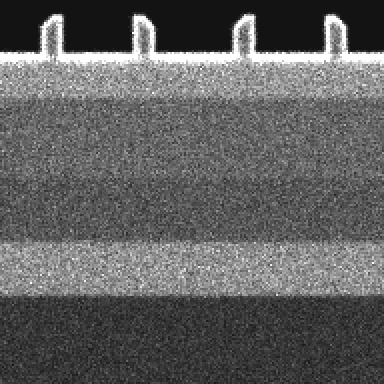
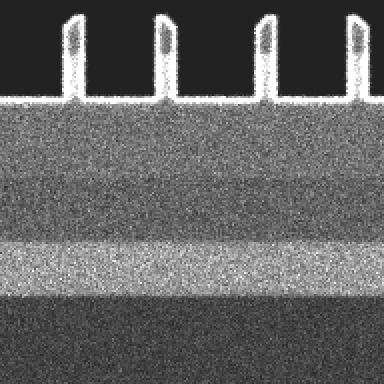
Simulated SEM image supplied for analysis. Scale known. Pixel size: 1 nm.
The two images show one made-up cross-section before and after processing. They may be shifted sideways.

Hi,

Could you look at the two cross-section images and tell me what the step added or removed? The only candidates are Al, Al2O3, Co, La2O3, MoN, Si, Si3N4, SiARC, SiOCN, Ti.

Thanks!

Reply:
removed Al2O3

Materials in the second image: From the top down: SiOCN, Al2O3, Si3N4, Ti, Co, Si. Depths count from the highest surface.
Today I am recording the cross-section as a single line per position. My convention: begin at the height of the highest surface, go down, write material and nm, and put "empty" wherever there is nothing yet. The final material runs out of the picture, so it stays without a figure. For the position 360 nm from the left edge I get empty 4, SiOCN 34, Al2O3 44, Si3N4 80, Ti 64, Co 54, Si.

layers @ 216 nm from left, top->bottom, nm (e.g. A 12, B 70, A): empty 82, Si3N4 80, Ti 64, Co 54, Si